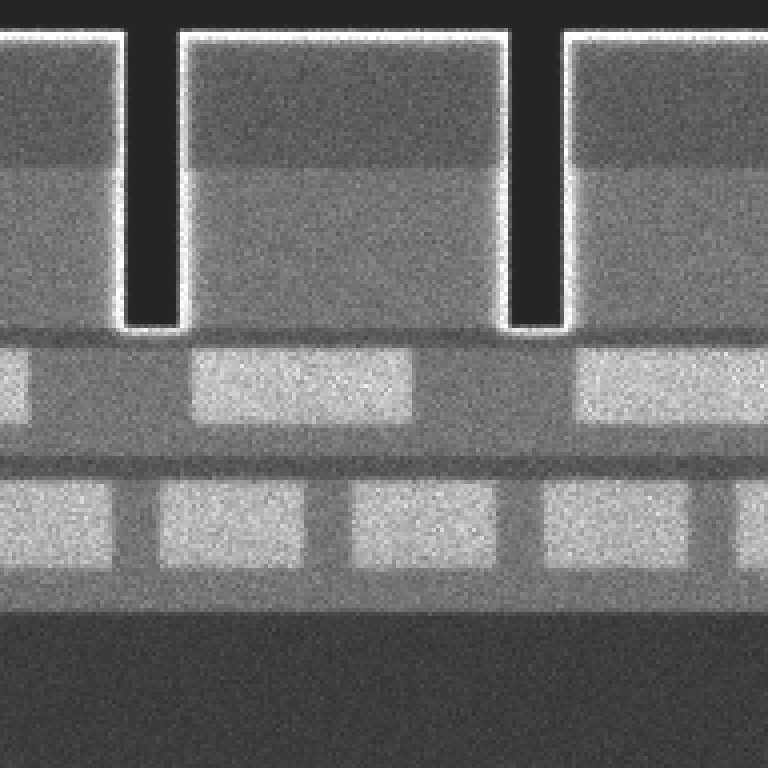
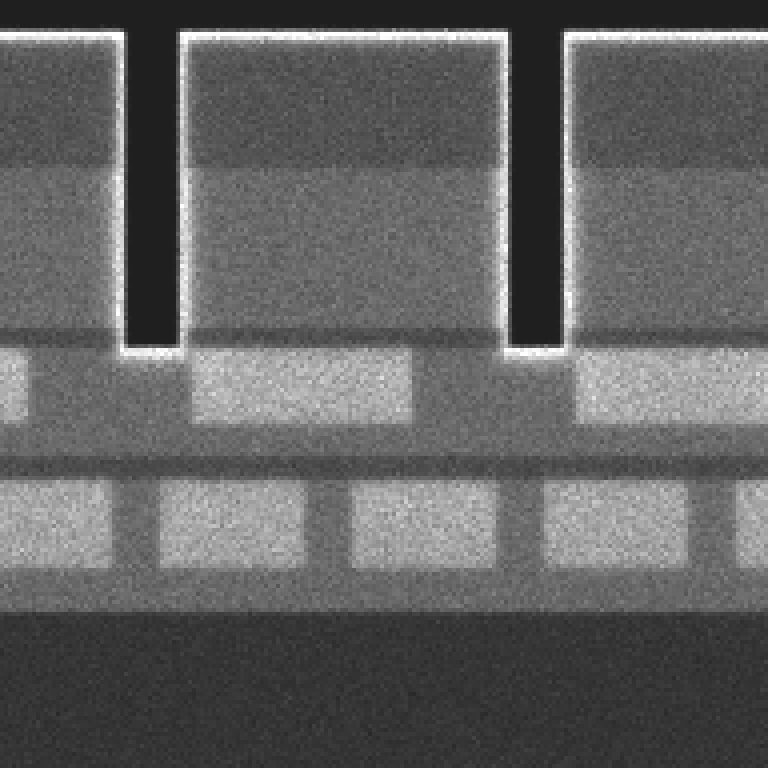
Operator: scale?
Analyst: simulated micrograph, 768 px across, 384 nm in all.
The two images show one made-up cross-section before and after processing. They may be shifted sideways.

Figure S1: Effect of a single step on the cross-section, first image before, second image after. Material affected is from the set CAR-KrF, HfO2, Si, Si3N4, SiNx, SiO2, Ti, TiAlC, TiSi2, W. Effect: removed SiNx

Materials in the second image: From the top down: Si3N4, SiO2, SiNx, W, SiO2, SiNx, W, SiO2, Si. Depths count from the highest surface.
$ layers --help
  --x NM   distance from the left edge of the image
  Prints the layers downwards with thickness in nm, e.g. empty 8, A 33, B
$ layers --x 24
Si3N4 68, SiO2 80, SiNx 10, SiO2 54, SiNx 12, W 44, SiO2 22, Si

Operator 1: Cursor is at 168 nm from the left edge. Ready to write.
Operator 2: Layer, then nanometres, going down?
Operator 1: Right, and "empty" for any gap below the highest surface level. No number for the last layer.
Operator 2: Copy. Si3N4 68, SiO2 80, SiNx 10, W 38, SiO2 16, SiNx 12, SiO2 66, Si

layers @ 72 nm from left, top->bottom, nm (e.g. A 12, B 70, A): empty 158, SiO2 54, SiNx 12, SiO2 66, Si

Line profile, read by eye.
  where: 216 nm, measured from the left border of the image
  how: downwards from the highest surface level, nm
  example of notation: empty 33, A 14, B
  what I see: Si3N4 68, SiO2 80, SiNx 10, SiO2 54, SiNx 12, W 44, SiO2 22, Si